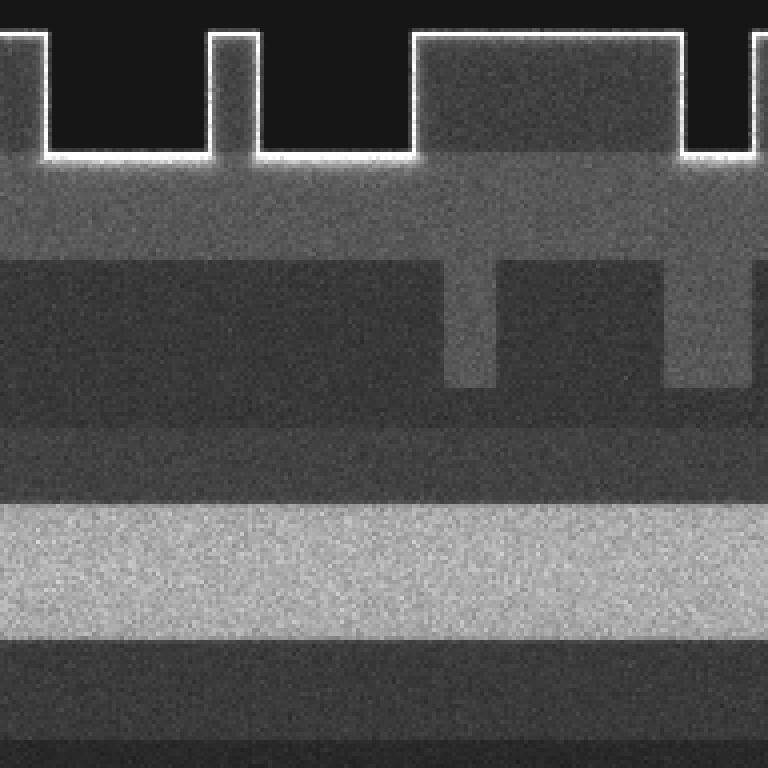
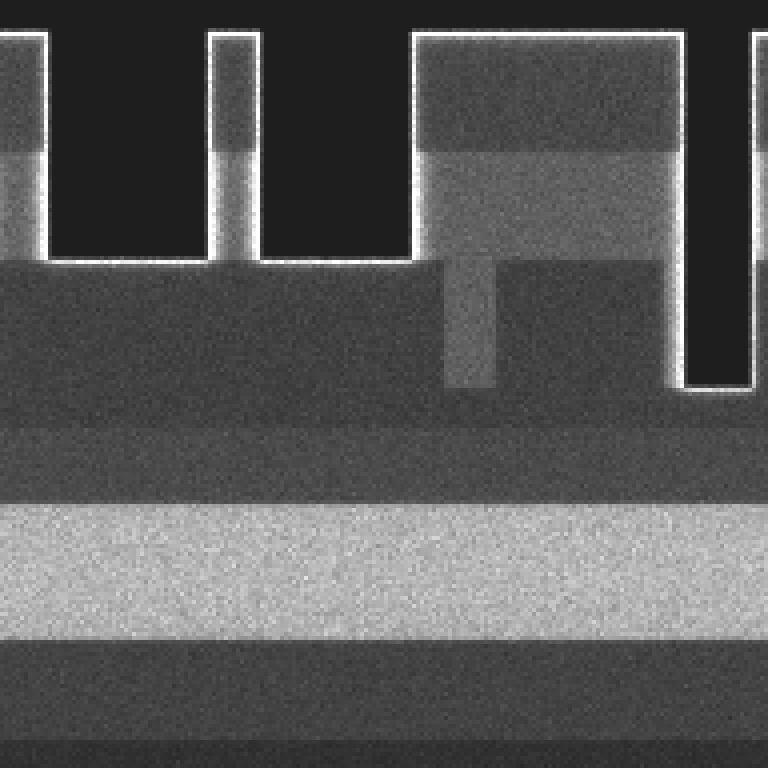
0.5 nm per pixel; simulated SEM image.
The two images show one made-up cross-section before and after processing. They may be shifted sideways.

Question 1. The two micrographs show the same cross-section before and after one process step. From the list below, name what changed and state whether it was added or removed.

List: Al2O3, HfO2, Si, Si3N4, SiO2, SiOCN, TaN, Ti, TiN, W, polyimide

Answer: SiO2, removed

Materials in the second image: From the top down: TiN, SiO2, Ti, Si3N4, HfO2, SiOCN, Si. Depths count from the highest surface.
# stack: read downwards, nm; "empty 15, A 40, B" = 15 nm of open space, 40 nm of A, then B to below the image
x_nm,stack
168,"empty 114, Ti 84, Si3N4 38, HfO2 68, SiOCN 50, Si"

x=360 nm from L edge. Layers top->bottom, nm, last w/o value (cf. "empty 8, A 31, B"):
empty 178, Ti 20, Si3N4 38, HfO2 68, SiOCN 50, Si